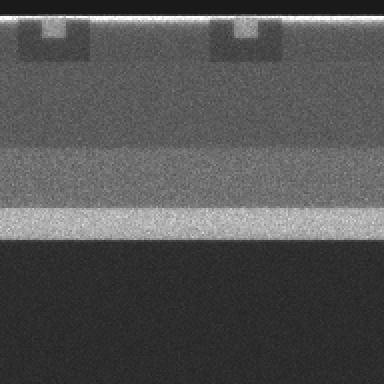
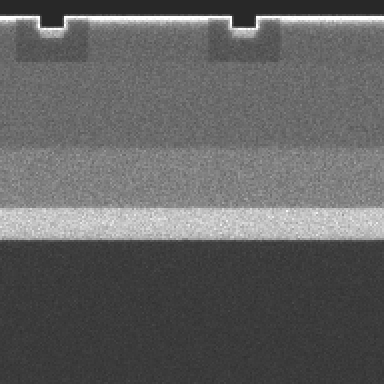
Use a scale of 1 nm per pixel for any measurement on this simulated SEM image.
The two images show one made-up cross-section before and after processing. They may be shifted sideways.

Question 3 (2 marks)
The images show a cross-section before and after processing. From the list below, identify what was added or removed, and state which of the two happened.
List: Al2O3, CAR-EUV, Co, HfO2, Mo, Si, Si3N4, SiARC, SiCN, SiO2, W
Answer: W was removed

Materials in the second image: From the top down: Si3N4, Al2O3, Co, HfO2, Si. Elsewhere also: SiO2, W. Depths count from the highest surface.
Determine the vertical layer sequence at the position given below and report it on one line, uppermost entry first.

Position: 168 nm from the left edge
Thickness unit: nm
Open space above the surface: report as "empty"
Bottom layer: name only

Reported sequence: SiO2 46, Al2O3 86, Co 60, HfO2 32, Si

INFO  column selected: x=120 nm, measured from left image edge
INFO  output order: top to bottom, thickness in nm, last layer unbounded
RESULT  SiO2 46, Al2O3 86, Co 60, HfO2 32, Si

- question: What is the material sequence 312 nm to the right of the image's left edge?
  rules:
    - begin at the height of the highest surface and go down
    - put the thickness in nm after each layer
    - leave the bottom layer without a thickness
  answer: SiO2 46, Al2O3 86, Co 60, HfO2 32, Si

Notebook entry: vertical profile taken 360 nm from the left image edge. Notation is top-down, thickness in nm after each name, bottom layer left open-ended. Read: SiO2 46, Al2O3 86, Co 60, HfO2 32, Si